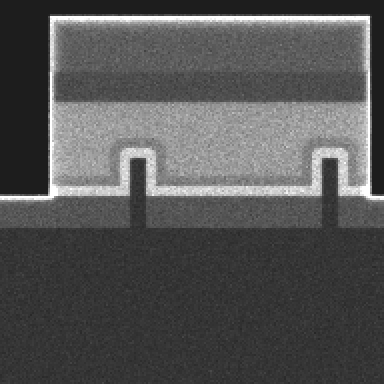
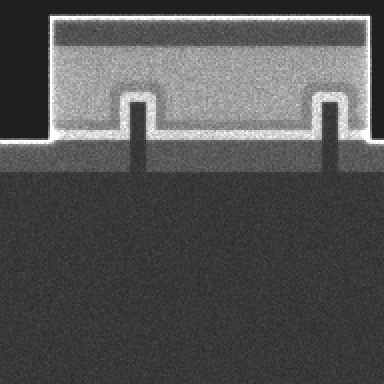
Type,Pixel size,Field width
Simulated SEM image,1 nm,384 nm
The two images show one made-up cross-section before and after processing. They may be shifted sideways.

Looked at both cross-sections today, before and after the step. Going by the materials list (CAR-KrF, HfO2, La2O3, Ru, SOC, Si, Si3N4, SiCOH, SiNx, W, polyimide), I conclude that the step removed SOC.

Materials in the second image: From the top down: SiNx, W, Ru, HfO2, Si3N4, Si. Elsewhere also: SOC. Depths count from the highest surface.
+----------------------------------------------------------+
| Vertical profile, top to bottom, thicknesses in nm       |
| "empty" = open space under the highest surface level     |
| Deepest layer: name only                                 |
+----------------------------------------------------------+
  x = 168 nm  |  SiNx 30, W 74, Ru 10, HfO2 10, Si3N4 32, Si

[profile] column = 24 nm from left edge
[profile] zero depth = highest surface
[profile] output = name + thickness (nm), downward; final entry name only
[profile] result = empty 124, Si3N4 32, Si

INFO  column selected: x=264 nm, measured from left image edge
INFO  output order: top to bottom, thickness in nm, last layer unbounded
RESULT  SiNx 30, W 74, Ru 10, HfO2 10, Si3N4 32, Si